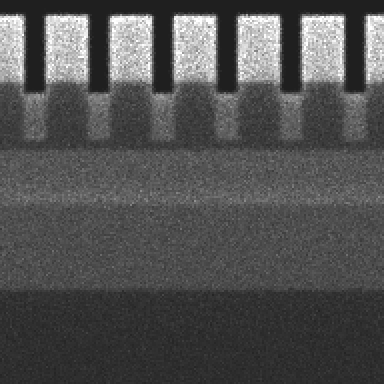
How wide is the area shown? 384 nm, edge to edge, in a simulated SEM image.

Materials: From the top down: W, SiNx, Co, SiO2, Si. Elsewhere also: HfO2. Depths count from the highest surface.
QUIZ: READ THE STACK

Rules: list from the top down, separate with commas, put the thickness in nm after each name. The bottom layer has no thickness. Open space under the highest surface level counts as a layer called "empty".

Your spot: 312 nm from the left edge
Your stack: HfO2 66, SiNx 68, Co 54, SiO2 86, Si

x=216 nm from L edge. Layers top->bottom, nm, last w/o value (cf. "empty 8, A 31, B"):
empty 78, W 46, SiNx 10, Co 54, SiO2 86, Si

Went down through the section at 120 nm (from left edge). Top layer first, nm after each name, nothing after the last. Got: HfO2 66, SiNx 68, Co 54, SiO2 86, Si